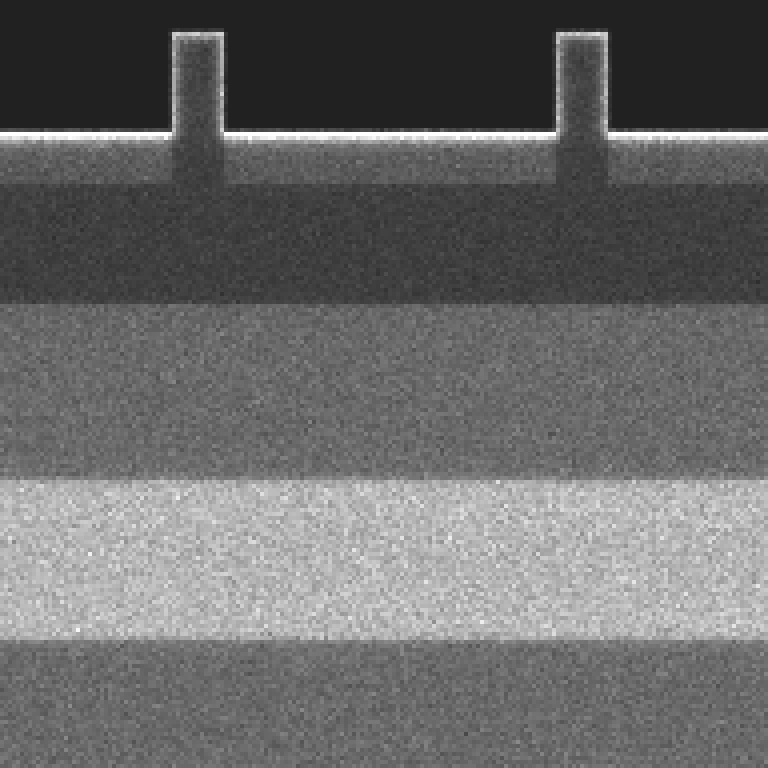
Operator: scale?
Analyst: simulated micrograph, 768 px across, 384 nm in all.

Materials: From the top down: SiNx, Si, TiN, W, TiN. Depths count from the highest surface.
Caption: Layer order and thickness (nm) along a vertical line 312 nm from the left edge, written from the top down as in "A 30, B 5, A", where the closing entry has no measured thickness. empty 50, SiNx 26, Si 60, TiN 88, W 80, TiN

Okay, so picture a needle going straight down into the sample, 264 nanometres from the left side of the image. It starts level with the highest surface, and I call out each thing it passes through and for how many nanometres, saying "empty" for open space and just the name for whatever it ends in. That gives empty 50, SiNx 26, Si 60, TiN 88, W 80, TiN